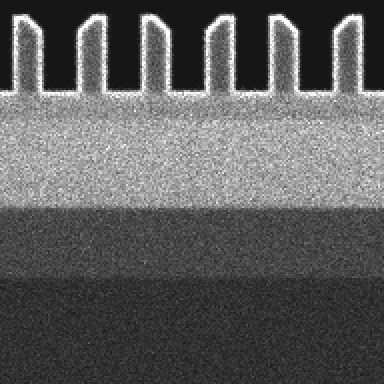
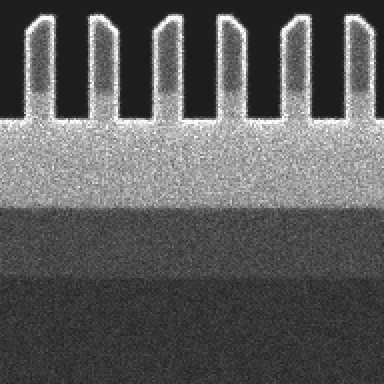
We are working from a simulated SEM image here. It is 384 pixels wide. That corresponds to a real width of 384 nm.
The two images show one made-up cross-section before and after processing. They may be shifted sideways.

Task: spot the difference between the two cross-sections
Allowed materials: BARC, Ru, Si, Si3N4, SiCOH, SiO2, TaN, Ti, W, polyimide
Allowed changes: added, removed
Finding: removed Ru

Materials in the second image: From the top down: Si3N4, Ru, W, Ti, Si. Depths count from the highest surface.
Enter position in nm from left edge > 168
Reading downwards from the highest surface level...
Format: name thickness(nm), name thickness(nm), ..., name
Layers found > Si3N4 76, Ru 28, W 88, Ti 70, Si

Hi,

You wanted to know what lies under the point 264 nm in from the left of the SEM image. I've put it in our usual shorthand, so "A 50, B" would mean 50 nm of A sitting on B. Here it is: empty 104, W 88, Ti 70, Si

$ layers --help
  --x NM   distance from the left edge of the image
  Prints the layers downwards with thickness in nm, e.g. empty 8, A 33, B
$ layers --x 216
empty 104, W 88, Ti 70, Si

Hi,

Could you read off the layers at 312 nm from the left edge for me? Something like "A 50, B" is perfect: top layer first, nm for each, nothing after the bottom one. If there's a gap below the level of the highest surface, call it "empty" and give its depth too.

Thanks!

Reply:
empty 104, W 88, Ti 70, Si